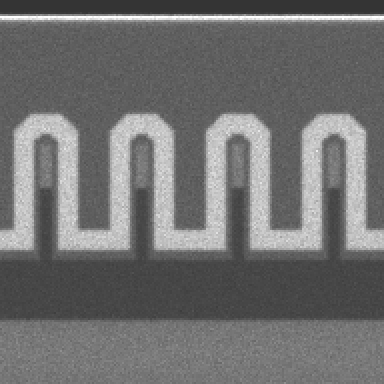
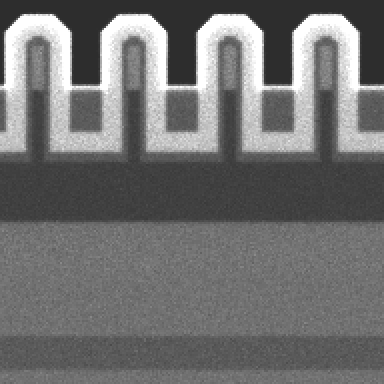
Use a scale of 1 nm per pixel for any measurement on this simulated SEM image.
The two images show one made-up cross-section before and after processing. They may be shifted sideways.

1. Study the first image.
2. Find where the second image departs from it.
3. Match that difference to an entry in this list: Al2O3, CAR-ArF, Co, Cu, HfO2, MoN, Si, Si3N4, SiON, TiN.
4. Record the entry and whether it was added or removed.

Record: Si3N4 / removed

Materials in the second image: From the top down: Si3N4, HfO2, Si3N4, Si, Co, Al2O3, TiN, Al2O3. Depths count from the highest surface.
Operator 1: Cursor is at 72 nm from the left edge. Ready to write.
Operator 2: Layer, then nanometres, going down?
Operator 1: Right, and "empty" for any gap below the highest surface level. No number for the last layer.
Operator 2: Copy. empty 70, Si3N4 46, HfO2 20, Si3N4 10, Si 60, Co 50, Al2O3 64, TiN 34, Al2O3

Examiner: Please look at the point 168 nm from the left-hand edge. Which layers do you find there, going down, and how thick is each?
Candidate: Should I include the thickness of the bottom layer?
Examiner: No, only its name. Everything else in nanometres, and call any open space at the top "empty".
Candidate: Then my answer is empty 70, Si3N4 46, HfO2 20, Si3N4 10, Si 60, Co 50, Al2O3 64, TiN 34, Al2O3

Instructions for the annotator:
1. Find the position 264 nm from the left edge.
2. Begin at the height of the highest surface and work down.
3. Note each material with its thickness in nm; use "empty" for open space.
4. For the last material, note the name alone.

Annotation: empty 70, Si3N4 46, HfO2 20, Si3N4 10, Si 60, Co 50, Al2O3 64, TiN 34, Al2O3